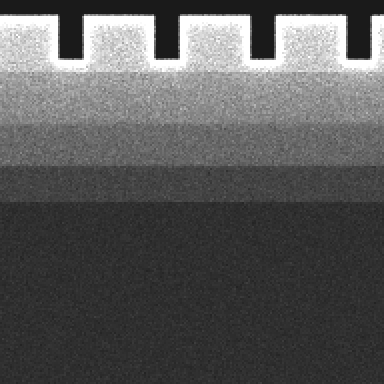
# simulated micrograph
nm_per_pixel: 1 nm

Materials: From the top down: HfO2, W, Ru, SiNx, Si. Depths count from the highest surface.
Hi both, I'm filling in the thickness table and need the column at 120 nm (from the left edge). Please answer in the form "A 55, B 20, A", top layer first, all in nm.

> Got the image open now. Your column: HfO2 56, W 52, Ru 42, SiNx 36, Si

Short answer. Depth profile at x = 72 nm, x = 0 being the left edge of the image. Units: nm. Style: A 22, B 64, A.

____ empty 44, HfO2 12, W 52, Ru 42, SiNx 36, Si